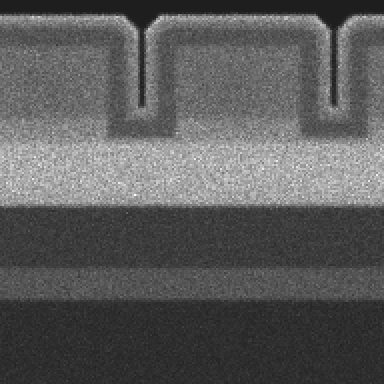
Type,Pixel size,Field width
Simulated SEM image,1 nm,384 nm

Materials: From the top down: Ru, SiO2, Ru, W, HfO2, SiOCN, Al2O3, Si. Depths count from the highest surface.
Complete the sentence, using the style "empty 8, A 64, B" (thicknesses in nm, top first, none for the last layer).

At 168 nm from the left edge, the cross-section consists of Ru 12, SiO2 110, W 6, HfO2 62, SiOCN 62, Al2O3 32, Si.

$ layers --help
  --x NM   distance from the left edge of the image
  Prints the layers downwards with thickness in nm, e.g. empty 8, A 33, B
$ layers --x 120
Ru 16, SiO2 106, W 6, HfO2 62, SiOCN 62, Al2O3 32, Si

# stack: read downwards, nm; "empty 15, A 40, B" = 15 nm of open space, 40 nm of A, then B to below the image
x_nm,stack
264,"Ru 12, SiO2 18, Ru 72, W 26, HfO2 62, SiOCN 62, Al2O3 32, Si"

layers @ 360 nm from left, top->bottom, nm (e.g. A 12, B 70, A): Ru 12, SiO2 110, W 6, HfO2 62, SiOCN 62, Al2O3 32, Si